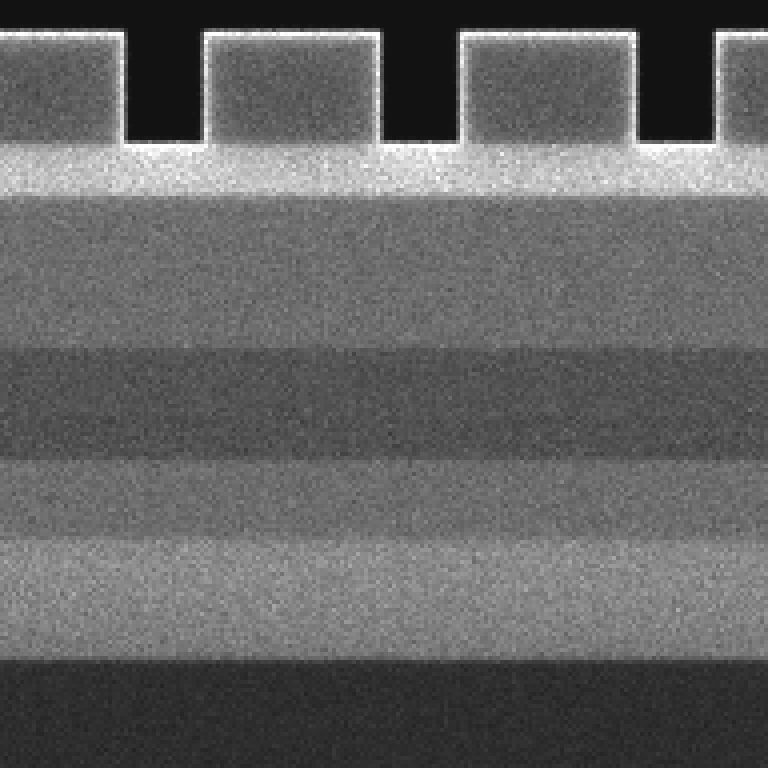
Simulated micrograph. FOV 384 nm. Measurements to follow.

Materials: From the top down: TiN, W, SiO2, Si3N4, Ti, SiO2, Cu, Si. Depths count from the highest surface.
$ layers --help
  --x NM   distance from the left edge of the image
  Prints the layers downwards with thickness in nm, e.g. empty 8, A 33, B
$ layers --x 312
TiN 56, W 26, SiO2 76, Si3N4 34, Ti 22, SiO2 40, Cu 60, Si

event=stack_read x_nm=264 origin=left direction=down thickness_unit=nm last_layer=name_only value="TiN 56, W 26, SiO2 76, Si3N4 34, Ti 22, SiO2 40, Cu 60, Si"